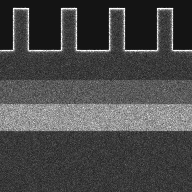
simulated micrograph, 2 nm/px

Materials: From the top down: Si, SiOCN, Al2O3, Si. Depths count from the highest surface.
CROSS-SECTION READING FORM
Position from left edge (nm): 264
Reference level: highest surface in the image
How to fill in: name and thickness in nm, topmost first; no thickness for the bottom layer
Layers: empty 84, Si 60, SiOCN 48, Al2O3 54, Si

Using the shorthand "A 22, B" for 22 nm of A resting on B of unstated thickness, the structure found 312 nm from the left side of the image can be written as empty 84, Si 60, SiOCN 48, Al2O3 54, Si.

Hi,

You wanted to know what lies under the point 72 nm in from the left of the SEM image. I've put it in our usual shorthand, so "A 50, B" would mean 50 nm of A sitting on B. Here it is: empty 84, Si 60, SiOCN 48, Al2O3 54, Si